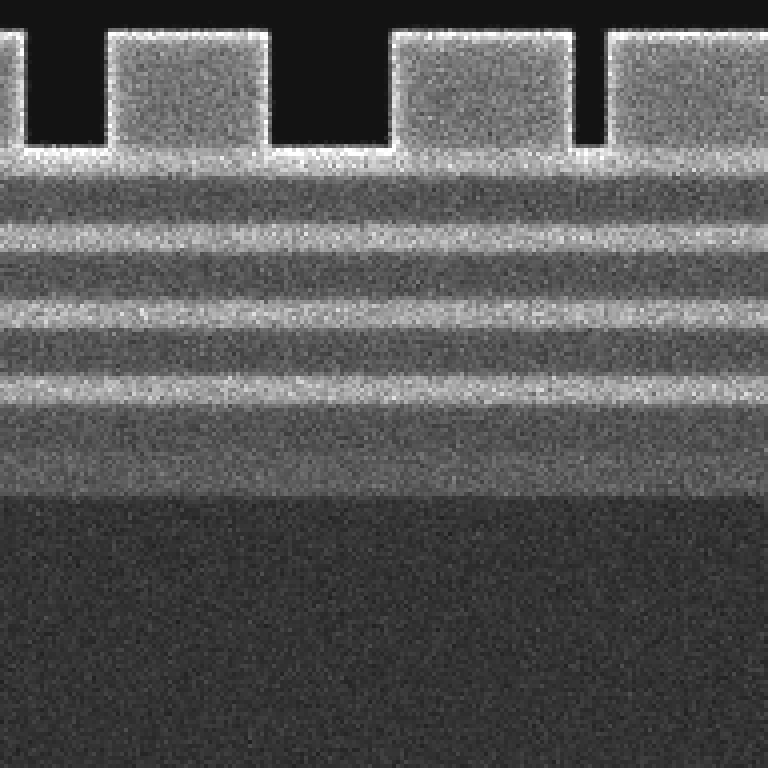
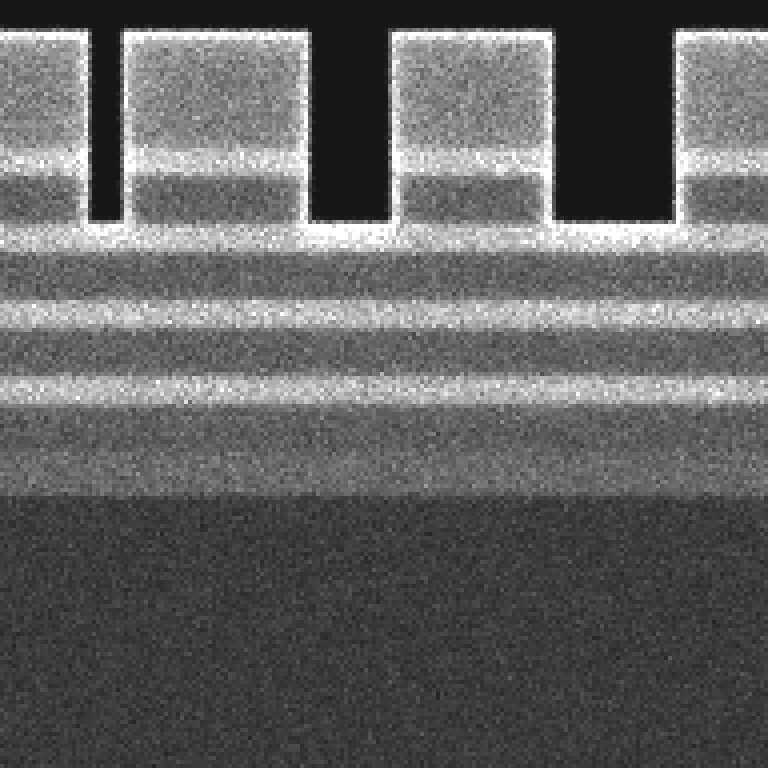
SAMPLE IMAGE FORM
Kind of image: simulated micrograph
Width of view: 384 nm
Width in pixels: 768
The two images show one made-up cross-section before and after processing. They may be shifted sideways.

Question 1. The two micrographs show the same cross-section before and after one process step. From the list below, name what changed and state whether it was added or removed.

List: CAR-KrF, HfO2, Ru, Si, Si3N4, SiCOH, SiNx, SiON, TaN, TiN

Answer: Ru and SiNx, removed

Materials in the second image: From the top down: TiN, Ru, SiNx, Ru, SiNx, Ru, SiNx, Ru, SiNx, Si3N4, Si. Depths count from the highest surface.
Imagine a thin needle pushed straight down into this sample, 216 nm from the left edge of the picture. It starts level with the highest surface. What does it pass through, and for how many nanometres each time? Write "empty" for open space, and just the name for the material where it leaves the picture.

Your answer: TiN 58, Ru 14, SiNx 24, Ru 14, SiNx 24, Ru 14, SiNx 24, Ru 14, SiNx 24, Si3N4 22, Si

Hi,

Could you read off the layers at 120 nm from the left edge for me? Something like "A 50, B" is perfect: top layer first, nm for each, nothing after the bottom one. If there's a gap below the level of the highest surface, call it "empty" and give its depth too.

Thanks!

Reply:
TiN 58, Ru 14, SiNx 24, Ru 14, SiNx 24, Ru 14, SiNx 24, Ru 14, SiNx 24, Si3N4 22, Si